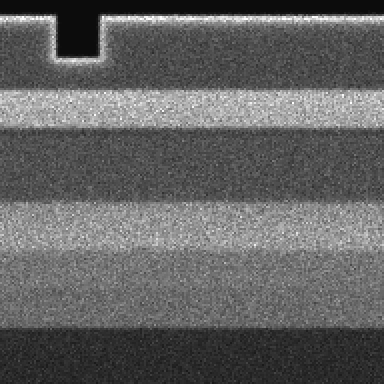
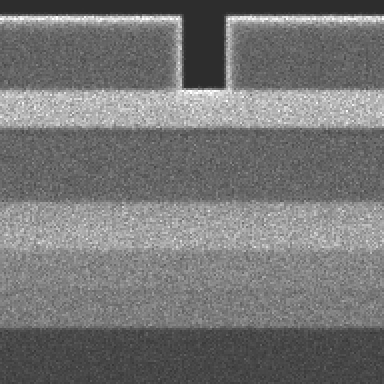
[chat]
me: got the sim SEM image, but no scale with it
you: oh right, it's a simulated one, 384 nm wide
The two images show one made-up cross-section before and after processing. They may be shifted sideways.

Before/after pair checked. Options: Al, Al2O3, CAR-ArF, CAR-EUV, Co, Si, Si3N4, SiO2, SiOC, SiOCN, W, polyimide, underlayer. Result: removed underlayer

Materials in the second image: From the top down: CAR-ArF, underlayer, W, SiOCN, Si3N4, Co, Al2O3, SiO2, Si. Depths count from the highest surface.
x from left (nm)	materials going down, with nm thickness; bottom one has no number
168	CAR-ArF 42, underlayer 32, W 38, SiOCN 8, Si3N4 66, Co 48, Al2O3 38, SiO2 40, Si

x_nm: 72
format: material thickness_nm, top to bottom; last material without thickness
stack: CAR-ArF 42, underlayer 32, W 38, SiOCN 8, Si3N4 66, Co 48, Al2O3 38, SiO2 40, Si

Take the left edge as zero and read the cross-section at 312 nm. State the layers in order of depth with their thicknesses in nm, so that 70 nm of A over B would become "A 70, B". CAR-ArF 42, underlayer 32, W 38, SiOCN 8, Si3N4 66, Co 48, Al2O3 38, SiO2 40, Si